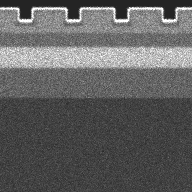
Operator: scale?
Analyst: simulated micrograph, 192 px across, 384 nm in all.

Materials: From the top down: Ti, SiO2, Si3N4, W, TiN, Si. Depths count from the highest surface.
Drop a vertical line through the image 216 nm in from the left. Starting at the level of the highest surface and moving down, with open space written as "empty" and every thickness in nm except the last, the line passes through Ti 6, SiO2 44, Si3N4 28, W 42, TiN 60, Si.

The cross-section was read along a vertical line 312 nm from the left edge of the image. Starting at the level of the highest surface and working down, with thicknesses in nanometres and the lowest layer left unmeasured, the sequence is Ti 6, SiO2 44, Si3N4 28, W 42, TiN 60, Si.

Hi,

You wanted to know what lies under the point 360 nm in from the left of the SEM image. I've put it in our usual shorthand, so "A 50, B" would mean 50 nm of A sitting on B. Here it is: Ti 6, SiO2 44, Si3N4 28, W 42, TiN 60, Si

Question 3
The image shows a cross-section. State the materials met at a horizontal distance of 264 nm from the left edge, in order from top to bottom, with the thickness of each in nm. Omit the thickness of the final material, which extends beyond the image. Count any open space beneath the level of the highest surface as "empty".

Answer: Ti 6, SiO2 44, Si3N4 28, W 42, TiN 60, Si